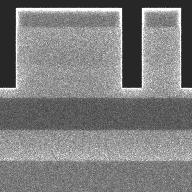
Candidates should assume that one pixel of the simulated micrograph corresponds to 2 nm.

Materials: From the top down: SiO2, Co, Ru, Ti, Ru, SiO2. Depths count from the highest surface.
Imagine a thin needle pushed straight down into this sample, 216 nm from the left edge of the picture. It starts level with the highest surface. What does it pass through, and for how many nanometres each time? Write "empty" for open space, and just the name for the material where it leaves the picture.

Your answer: SiO2 38, Co 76, Ru 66, Ti 64, Ru 62, SiO2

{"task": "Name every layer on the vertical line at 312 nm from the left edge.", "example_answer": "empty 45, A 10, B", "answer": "SiO2 38, Co 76, Ru 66, Ti 64, Ru 62, SiO2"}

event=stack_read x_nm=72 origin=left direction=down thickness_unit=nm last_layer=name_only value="SiO2 38, Co 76, Ru 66, Ti 64, Ru 62, SiO2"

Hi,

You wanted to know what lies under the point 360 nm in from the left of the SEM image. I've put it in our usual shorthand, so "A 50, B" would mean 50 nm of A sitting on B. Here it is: SiO2 38, Co 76, Ru 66, Ti 64, Ru 62, SiO2